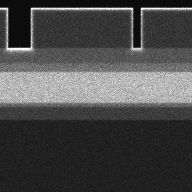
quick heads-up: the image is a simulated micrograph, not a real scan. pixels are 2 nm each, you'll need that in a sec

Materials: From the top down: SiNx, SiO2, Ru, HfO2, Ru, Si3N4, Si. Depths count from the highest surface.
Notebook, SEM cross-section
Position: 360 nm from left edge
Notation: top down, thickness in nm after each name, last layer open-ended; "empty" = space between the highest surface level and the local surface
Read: SiNx 80, SiO2 30, Ru 18, HfO2 62, Ru 8, Si3N4 26, Si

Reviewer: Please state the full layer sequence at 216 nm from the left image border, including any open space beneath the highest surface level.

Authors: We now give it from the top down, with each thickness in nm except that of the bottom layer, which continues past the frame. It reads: SiNx 80, SiO2 30, Ru 18, HfO2 62, Ru 8, Si3N4 26, Si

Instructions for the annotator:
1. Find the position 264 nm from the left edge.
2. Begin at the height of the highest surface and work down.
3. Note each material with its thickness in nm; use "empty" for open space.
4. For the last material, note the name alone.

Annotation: SiNx 80, SiO2 30, Ru 18, HfO2 62, Ru 8, Si3N4 26, Si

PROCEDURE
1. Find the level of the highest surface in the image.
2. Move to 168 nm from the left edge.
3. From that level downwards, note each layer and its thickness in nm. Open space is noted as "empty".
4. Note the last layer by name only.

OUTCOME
SiNx 80, SiO2 30, Ru 18, HfO2 62, Ru 8, Si3N4 26, Si